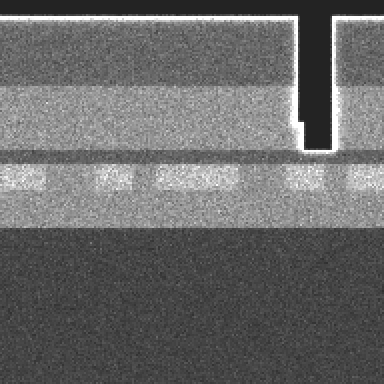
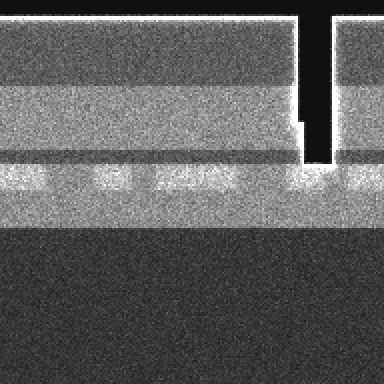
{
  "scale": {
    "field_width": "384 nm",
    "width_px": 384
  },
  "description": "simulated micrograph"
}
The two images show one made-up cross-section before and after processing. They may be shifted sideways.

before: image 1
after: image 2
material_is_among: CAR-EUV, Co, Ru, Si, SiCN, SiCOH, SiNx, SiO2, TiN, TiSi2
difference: SiCN, removed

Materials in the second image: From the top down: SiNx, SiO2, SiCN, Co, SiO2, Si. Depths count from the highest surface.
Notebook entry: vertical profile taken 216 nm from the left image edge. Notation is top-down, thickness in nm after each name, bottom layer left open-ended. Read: SiNx 70, SiO2 64, SiCN 14, Co 26, SiO2 38, Si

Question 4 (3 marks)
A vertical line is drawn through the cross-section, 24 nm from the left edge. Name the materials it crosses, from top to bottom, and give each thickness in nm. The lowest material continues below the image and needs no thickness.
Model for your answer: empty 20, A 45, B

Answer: SiNx 70, SiO2 64, SiCN 14, Co 26, SiO2 38, Si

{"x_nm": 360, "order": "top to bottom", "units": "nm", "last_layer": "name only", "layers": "SiNx 70, SiO2 64, SiCN 14, Co 26, SiO2 38, Si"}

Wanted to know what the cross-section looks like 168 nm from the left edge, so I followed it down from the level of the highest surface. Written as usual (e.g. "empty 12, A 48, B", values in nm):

SiNx 70, SiO2 64, SiCN 14, Co 26, SiO2 38, Si